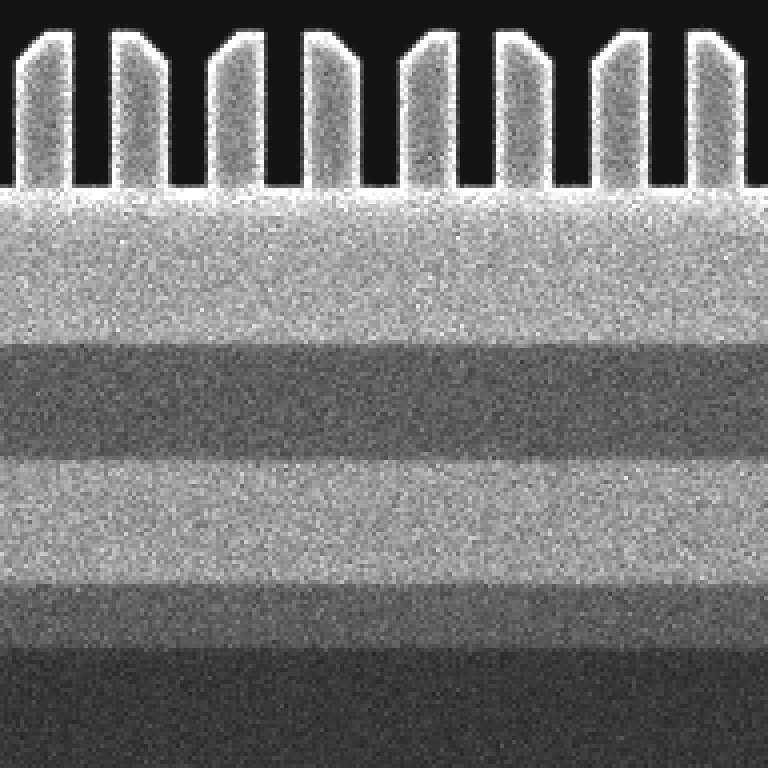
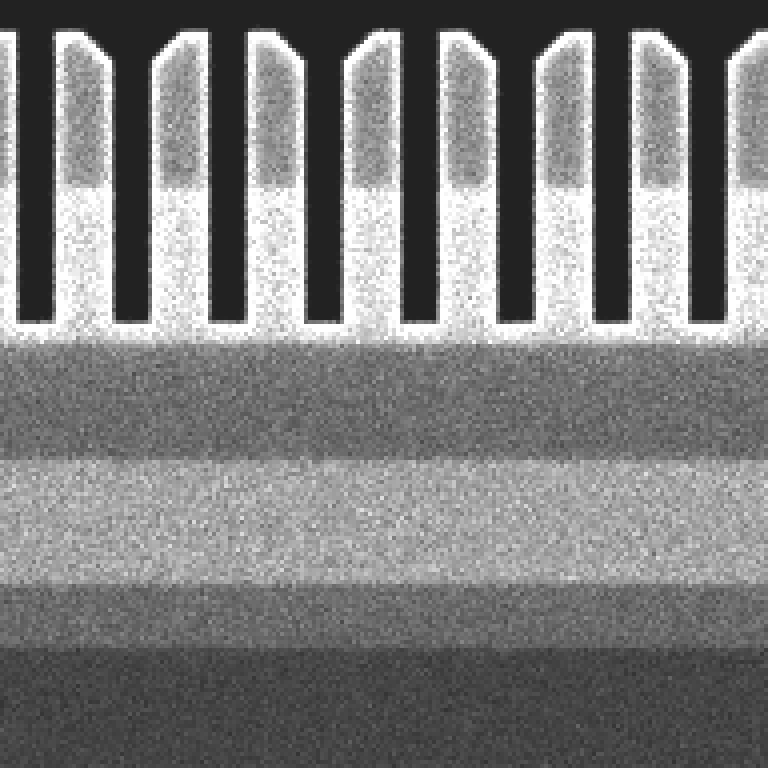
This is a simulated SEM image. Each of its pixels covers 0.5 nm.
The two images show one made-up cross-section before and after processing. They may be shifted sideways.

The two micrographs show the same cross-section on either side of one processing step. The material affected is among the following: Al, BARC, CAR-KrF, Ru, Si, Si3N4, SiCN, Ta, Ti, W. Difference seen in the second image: W removed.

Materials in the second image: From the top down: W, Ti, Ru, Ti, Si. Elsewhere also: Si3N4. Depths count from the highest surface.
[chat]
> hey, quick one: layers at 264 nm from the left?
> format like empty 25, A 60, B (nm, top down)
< empty 146, W 10, Ti 58, Ru 62, Ti 32, Si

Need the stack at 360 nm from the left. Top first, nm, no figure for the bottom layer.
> empty 146, W 10, Ti 58, Ru 62, Ti 32, Si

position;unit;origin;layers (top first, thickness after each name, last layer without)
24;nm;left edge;empty 146, W 10, Ti 58, Ru 62, Ti 32, Si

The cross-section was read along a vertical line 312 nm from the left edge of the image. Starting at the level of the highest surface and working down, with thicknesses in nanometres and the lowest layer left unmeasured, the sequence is empty 146, W 10, Ti 58, Ru 62, Ti 32, Si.